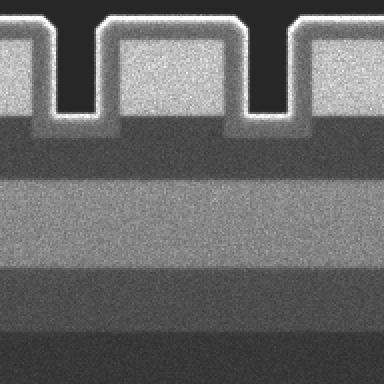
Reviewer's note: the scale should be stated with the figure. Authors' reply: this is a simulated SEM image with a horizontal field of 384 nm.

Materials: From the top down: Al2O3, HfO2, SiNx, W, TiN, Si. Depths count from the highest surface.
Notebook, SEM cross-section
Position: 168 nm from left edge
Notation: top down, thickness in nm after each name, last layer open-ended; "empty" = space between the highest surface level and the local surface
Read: Al2O3 24, HfO2 76, SiNx 64, W 88, TiN 64, Si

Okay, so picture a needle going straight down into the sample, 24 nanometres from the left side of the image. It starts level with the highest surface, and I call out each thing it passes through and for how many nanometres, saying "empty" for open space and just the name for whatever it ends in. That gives Al2O3 24, HfO2 76, SiNx 64, W 88, TiN 64, Si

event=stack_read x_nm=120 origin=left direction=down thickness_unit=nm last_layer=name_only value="Al2O3 24, HfO2 76, SiNx 64, W 88, TiN 64, Si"